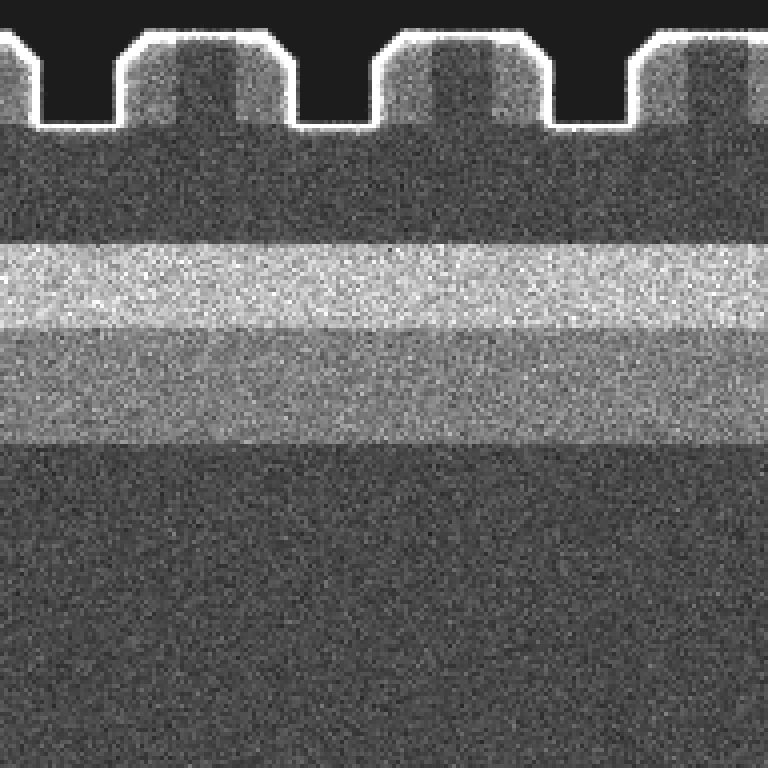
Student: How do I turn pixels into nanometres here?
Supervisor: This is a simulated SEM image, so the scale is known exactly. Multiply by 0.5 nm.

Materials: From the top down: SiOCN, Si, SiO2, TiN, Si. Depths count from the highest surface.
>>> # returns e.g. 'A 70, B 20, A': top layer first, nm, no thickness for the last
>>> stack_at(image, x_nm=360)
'Si 106, SiO2 42, TiN 58, Si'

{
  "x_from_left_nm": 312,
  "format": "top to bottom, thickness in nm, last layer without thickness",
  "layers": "empty 46, Si 60, SiO2 42, TiN 58, Si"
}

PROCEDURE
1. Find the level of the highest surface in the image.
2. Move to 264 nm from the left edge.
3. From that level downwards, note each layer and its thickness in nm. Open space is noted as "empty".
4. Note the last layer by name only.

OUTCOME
empty 4, SiOCN 42, Si 60, SiO2 42, TiN 58, Si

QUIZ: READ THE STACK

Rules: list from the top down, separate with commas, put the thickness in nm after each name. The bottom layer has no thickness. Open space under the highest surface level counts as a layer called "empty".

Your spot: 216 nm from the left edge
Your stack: Si 106, SiO2 42, TiN 58, Si